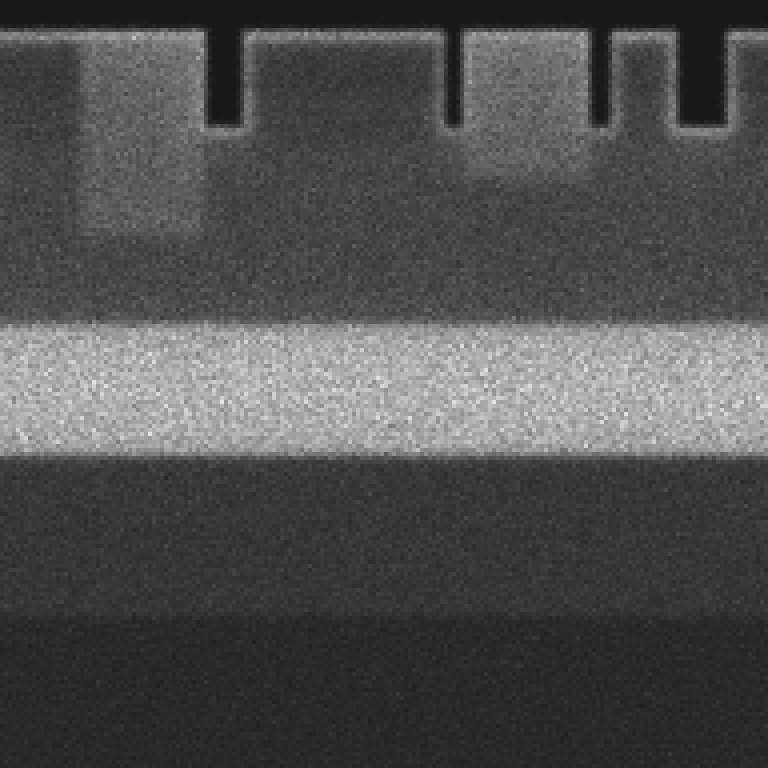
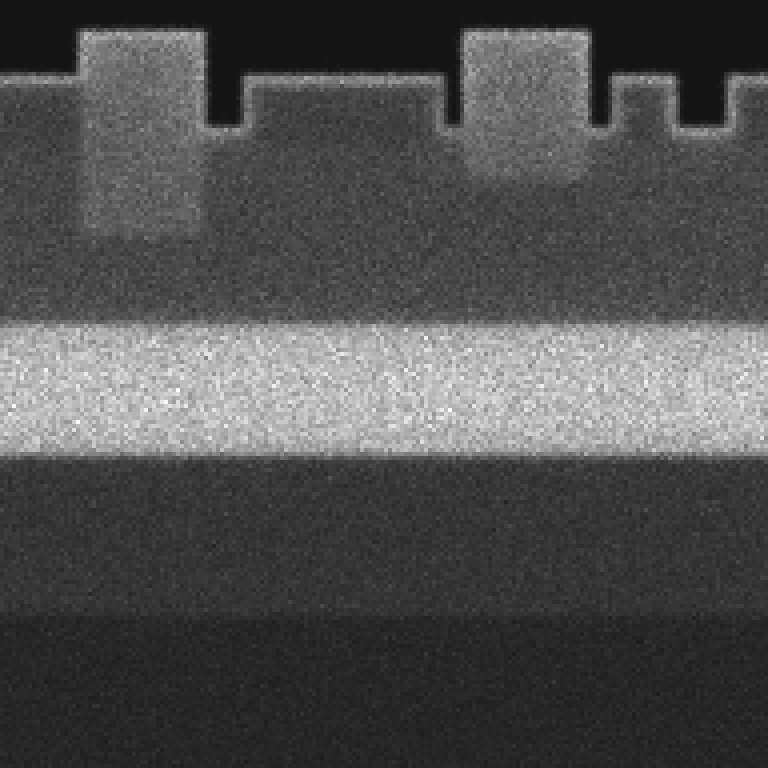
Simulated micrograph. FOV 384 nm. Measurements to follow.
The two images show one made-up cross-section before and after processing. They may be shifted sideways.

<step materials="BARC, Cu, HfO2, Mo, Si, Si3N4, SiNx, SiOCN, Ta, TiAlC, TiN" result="removed SiNx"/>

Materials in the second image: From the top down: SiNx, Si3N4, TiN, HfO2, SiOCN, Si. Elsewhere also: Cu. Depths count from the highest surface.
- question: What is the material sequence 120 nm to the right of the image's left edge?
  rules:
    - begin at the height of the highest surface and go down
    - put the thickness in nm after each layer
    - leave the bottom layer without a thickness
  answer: empty 48, Si3N4 8, TiN 90, HfO2 66, SiOCN 80, Si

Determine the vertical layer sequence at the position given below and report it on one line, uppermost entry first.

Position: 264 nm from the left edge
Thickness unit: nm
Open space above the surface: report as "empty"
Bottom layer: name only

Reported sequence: Cu 74, TiN 72, HfO2 66, SiOCN 80, Si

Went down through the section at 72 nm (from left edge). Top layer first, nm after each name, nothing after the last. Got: Cu 102, TiN 44, HfO2 66, SiOCN 80, Si